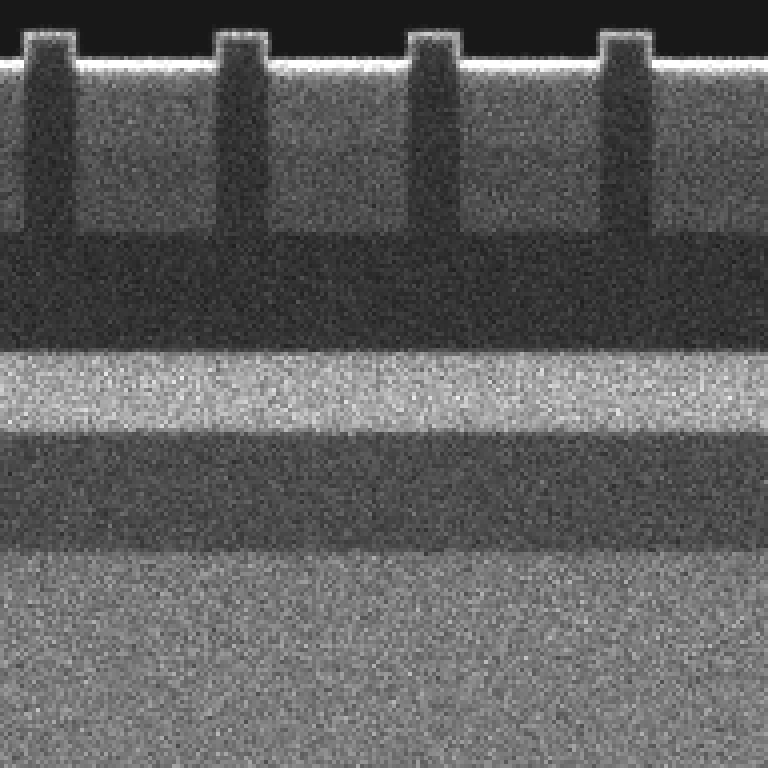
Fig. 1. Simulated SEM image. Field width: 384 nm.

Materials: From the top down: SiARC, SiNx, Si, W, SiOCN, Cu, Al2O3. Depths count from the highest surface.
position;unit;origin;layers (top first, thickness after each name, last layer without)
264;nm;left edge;empty 14, SiARC 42, SiNx 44, Si 60, W 40, SiOCN 60, Cu 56, Al2O3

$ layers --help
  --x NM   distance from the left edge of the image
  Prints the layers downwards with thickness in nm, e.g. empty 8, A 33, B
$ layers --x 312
Si 160, W 40, SiOCN 60, Cu 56, Al2O3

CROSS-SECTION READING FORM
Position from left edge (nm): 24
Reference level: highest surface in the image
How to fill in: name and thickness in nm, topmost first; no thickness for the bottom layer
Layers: Si 160, W 40, SiOCN 60, Cu 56, Al2O3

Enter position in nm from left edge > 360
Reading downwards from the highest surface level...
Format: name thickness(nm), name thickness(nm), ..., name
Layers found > empty 14, SiARC 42, SiNx 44, Si 60, W 40, SiOCN 60, Cu 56, Al2O3